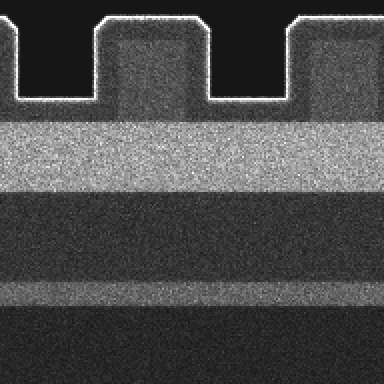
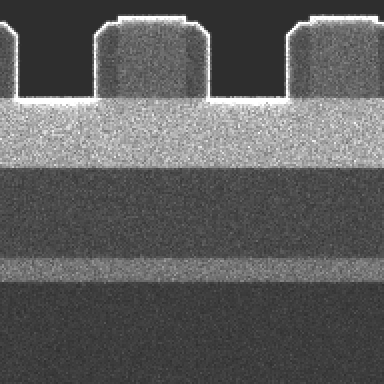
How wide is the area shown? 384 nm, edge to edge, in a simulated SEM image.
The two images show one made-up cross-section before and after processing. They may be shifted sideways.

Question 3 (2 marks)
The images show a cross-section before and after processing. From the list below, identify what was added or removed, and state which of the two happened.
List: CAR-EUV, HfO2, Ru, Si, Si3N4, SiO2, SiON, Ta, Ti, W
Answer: Si3N4 was removed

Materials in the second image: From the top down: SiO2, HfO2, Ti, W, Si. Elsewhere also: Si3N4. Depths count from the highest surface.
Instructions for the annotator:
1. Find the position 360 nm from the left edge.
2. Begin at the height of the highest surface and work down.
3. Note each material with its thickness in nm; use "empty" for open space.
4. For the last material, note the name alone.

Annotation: SiO2 82, HfO2 70, Ti 90, W 24, Si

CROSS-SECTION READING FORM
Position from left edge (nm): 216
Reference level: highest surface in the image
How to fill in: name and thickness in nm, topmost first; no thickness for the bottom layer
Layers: empty 82, HfO2 70, Ti 90, W 24, Si